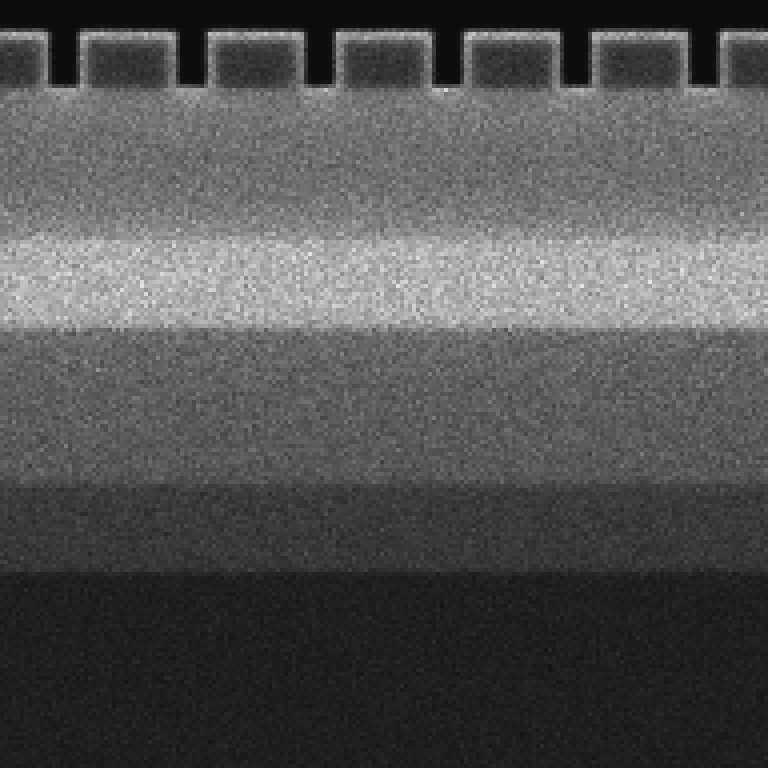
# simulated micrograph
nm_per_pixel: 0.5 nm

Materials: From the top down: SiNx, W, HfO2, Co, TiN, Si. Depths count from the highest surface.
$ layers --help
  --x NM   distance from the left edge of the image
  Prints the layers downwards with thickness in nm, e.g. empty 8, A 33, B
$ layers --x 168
SiNx 28, W 76, HfO2 44, Co 78, TiN 44, Si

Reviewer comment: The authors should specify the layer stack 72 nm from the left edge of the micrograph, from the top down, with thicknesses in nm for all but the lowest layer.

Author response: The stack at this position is SiNx 28, W 76, HfO2 44, Co 78, TiN 44, Si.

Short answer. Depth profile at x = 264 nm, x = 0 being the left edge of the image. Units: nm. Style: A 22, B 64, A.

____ SiNx 28, W 76, HfO2 44, Co 78, TiN 44, Si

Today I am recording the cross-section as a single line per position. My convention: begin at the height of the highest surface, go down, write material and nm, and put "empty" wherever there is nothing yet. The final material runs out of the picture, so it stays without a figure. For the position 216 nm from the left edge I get empty 28, W 76, HfO2 44, Co 78, TiN 44, Si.